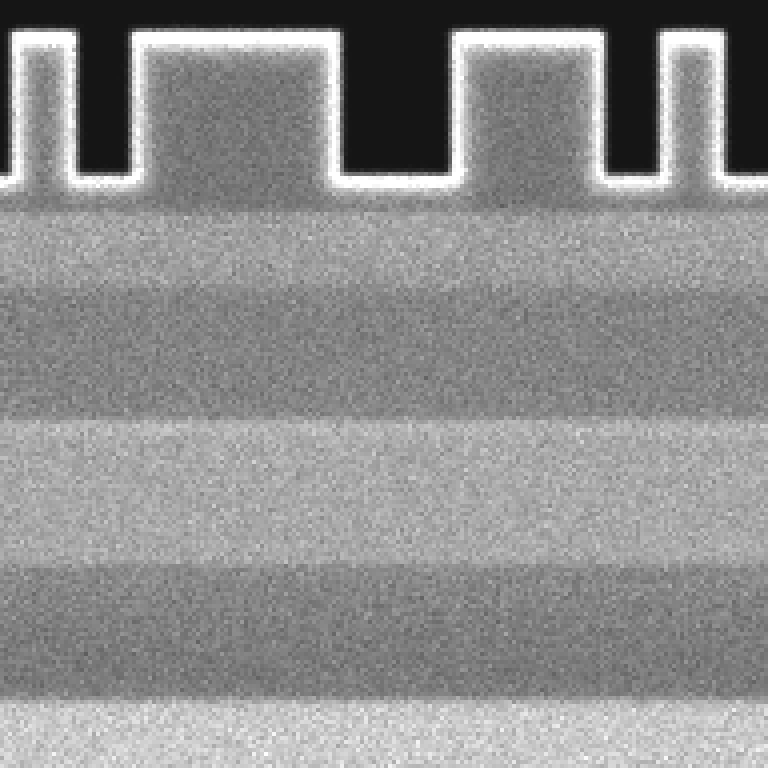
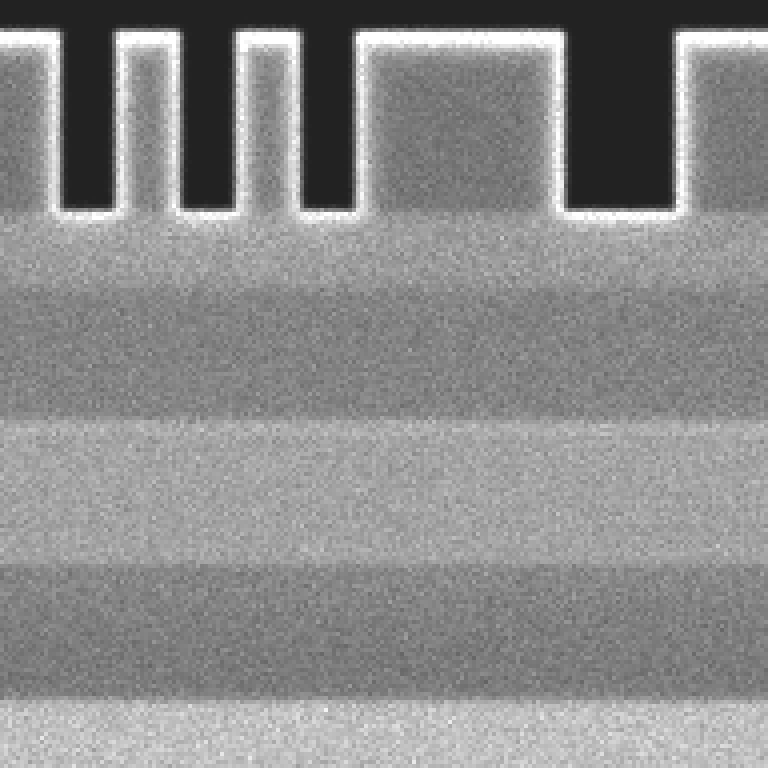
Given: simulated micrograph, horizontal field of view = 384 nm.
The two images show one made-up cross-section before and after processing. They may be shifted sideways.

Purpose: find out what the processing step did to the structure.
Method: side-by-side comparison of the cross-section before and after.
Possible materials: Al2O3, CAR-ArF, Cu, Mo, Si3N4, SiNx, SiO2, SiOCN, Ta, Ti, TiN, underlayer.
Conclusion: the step removed underlayer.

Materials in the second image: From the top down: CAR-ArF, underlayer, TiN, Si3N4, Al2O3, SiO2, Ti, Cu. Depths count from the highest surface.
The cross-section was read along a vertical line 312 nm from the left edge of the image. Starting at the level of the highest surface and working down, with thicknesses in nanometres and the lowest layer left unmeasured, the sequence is empty 90, TiN 38, Si3N4 66, Al2O3 8, SiO2 64, Ti 68, Cu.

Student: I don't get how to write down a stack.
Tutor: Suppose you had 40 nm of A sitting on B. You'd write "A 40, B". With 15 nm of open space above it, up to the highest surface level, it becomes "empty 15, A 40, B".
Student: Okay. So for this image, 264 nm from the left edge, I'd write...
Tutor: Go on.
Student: CAR-ArF 72, underlayer 18, TiN 38, Si3N4 66, Al2O3 8, SiO2 64, Ti 68, Cu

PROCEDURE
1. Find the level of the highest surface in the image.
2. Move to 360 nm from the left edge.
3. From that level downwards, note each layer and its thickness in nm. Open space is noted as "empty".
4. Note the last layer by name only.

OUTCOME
CAR-ArF 72, underlayer 18, TiN 38, Si3N4 66, Al2O3 8, SiO2 64, Ti 68, Cu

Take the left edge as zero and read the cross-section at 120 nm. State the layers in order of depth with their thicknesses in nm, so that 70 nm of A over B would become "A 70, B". CAR-ArF 72, underlayer 18, TiN 38, Si3N4 66, Al2O3 8, SiO2 64, Ti 68, Cu